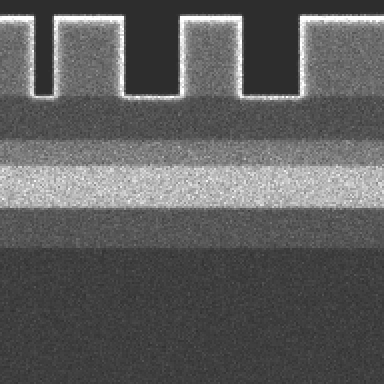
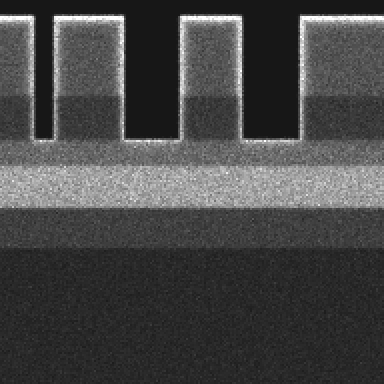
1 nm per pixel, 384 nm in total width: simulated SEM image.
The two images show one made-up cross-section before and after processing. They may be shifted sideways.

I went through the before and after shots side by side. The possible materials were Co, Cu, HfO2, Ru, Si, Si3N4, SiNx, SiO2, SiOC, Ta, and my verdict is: removed, SiNx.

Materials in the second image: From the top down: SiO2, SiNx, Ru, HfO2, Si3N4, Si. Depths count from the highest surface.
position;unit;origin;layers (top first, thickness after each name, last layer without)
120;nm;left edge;SiO2 80, SiNx 44, Ru 26, HfO2 42, Si3N4 40, Si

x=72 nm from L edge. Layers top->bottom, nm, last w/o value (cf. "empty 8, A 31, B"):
SiO2 80, SiNx 44, Ru 26, HfO2 42, Si3N4 40, Si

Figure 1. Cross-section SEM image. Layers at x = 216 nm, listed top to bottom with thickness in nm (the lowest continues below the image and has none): SiO2 80, SiNx 44, Ru 26, HfO2 42, Si3N4 40, Si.